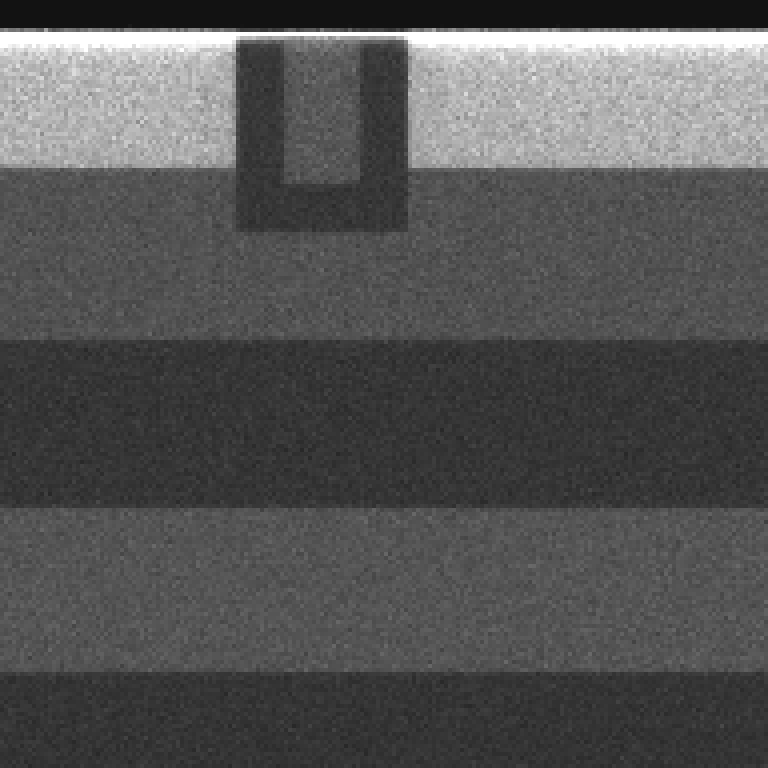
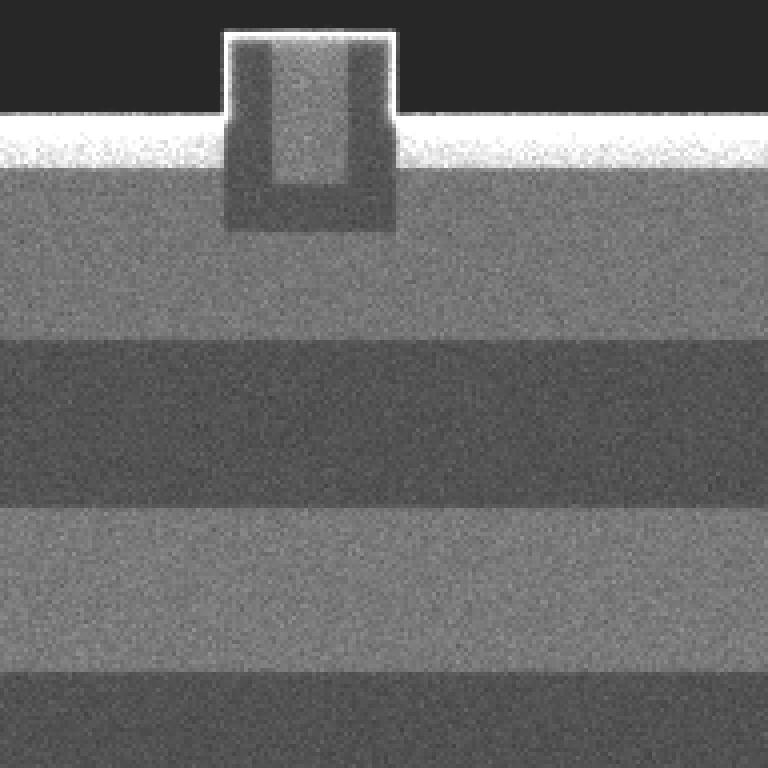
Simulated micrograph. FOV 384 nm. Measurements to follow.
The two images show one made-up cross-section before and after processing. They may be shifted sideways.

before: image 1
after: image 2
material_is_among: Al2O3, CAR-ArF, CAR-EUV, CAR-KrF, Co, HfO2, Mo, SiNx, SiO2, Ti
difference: HfO2, removed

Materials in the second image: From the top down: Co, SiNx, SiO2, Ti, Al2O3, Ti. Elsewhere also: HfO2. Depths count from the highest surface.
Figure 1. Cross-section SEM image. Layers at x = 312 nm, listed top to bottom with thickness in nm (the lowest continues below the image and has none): empty 42, HfO2 26, SiO2 86, Ti 84, Al2O3 82, Ti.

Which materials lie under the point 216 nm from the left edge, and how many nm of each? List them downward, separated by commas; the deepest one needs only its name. empty 42, HfO2 26, SiO2 86, Ti 84, Al2O3 82, Ti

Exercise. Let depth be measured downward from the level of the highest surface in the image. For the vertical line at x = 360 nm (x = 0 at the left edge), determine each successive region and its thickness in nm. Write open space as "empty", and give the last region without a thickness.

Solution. empty 42, HfO2 26, SiO2 86, Ti 84, Al2O3 82, Ti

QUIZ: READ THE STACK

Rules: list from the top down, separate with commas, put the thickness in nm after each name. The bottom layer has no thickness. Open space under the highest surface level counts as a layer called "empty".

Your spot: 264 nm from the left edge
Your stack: empty 42, HfO2 26, SiO2 86, Ti 84, Al2O3 82, Ti